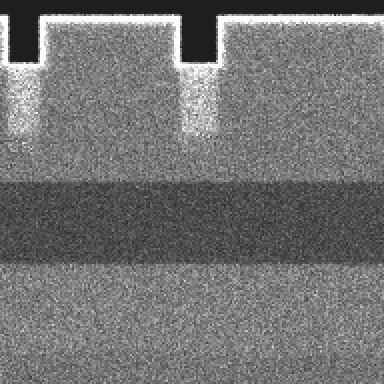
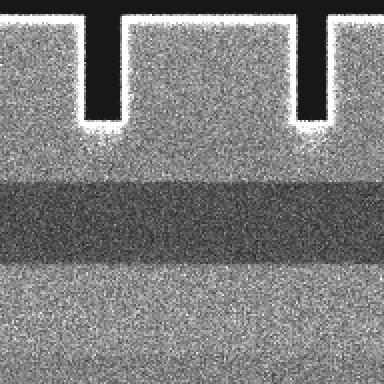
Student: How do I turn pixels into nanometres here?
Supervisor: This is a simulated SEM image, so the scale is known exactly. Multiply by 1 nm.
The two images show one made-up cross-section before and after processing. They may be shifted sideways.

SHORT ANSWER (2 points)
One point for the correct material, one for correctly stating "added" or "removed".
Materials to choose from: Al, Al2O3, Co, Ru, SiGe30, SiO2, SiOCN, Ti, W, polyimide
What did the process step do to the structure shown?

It removed W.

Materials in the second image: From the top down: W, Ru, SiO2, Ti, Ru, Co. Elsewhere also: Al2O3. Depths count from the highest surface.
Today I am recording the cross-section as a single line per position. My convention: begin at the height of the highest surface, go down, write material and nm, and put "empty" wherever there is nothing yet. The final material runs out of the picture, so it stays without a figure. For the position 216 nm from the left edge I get Al2O3 88, SiO2 78, Ti 82, Ru 90, Co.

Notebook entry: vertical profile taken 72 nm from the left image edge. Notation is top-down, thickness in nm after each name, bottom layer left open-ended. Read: Al2O3 88, SiO2 78, Ti 82, Ru 90, Co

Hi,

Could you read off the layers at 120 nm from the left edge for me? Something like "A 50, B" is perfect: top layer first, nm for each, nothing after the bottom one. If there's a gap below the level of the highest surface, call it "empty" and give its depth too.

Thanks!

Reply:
empty 106, W 12, Ru 20, SiO2 28, Ti 82, Ru 90, Co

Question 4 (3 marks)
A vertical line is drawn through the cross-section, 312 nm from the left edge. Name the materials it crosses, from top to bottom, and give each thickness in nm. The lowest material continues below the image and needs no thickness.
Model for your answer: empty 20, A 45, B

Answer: empty 106, W 12, Ru 20, SiO2 28, Ti 82, Ru 90, Co